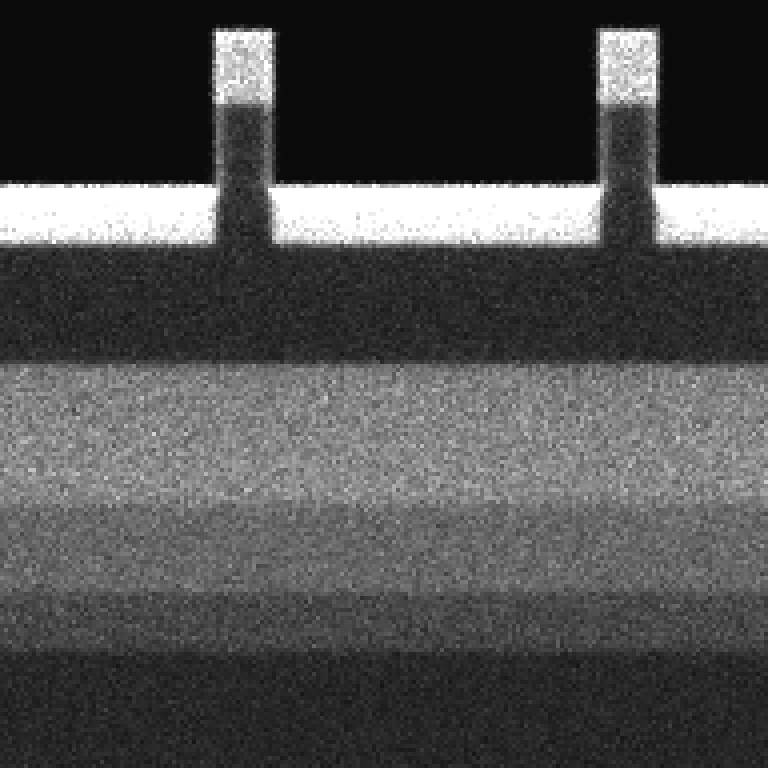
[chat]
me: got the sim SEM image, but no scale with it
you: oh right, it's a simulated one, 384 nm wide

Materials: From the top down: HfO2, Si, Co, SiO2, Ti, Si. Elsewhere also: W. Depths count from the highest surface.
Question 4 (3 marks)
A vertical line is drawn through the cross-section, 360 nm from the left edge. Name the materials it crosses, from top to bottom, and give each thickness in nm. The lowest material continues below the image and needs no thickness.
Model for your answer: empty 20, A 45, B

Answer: empty 78, HfO2 28, Si 60, Co 70, SiO2 44, Ti 30, Si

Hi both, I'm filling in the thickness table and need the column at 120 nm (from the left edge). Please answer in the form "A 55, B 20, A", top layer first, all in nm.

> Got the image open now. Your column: W 36, Si 130, Co 70, SiO2 44, Ti 30, Si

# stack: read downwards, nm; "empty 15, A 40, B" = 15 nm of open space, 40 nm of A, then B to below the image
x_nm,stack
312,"W 36, Si 130, Co 70, SiO2 44, Ti 30, Si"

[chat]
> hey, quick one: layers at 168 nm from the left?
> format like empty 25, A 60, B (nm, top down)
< empty 78, HfO2 28, Si 60, Co 70, SiO2 44, Ti 30, Si